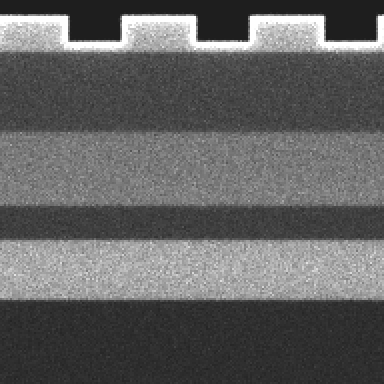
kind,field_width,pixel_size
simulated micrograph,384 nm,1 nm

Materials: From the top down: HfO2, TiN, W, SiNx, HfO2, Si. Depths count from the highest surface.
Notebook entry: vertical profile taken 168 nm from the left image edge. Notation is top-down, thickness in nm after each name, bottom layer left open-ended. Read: HfO2 36, TiN 80, W 74, SiNx 34, HfO2 60, Si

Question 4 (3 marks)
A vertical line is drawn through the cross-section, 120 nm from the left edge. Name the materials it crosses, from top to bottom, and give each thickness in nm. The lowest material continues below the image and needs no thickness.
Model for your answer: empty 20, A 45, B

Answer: empty 26, HfO2 10, TiN 80, W 74, SiNx 34, HfO2 60, Si